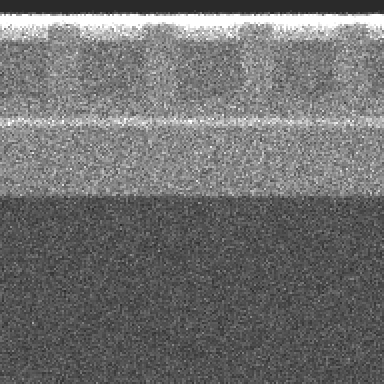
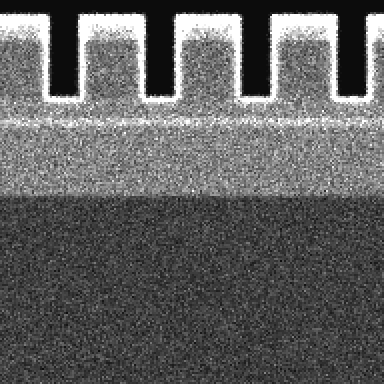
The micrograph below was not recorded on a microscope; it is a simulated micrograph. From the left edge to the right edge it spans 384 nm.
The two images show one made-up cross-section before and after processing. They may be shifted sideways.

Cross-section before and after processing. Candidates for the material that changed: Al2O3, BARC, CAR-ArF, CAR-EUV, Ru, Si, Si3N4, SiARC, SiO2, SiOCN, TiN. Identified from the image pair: SiARC (removed).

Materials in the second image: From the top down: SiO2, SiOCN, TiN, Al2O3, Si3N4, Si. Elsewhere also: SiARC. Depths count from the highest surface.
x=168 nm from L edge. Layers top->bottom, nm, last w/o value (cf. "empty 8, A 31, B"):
empty 82, TiN 20, Al2O3 8, Si3N4 70, Si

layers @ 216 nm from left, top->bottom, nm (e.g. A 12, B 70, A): SiO2 24, SiOCN 58, TiN 20, Al2O3 8, Si3N4 70, Si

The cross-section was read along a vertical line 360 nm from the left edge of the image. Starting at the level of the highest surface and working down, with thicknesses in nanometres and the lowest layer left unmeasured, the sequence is empty 82, TiN 20, Al2O3 8, Si3N4 70, Si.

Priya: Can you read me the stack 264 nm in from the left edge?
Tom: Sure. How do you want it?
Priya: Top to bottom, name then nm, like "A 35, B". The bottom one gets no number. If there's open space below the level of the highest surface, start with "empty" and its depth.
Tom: empty 82, TiN 20, Al2O3 8, Si3N4 70, Si